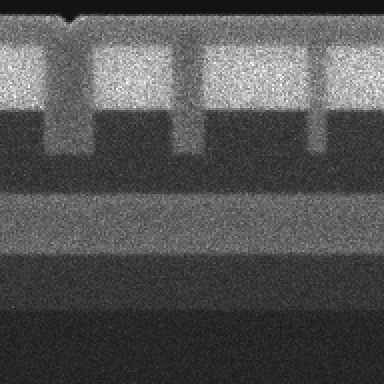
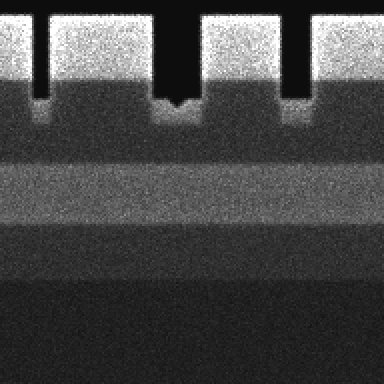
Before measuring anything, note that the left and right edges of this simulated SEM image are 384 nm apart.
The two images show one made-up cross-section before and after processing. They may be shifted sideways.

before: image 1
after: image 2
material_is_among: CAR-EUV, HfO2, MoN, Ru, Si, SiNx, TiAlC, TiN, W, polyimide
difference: Ru, removed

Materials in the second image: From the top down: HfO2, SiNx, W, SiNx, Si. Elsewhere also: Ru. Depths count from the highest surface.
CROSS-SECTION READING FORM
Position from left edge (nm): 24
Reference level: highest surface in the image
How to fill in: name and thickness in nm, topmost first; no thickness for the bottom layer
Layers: HfO2 64, SiNx 84, W 60, SiNx 56, Si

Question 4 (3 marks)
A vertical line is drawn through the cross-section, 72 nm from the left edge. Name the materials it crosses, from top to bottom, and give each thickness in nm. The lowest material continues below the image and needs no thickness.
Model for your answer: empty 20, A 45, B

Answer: HfO2 64, SiNx 84, W 60, SiNx 56, Si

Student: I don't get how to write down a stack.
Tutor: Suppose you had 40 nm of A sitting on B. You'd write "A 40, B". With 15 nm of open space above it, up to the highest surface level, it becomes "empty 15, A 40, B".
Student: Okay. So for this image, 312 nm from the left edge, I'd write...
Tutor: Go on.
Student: HfO2 64, SiNx 84, W 60, SiNx 56, Si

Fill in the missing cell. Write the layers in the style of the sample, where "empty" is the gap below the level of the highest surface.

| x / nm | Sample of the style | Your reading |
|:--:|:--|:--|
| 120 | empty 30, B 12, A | HfO2 64, SiNx 84, W 60, SiNx 56, Si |